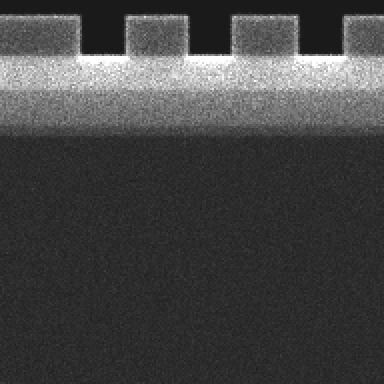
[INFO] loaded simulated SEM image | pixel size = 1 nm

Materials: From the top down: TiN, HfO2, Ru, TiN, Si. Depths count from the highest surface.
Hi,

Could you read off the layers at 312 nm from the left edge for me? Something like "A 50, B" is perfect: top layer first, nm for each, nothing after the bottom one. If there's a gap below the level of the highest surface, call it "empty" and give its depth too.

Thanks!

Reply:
empty 40, HfO2 34, Ru 36, TiN 10, Si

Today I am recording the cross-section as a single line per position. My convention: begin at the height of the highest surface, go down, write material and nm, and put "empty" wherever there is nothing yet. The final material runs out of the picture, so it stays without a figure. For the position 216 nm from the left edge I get empty 40, HfO2 34, Ru 36, TiN 10, Si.